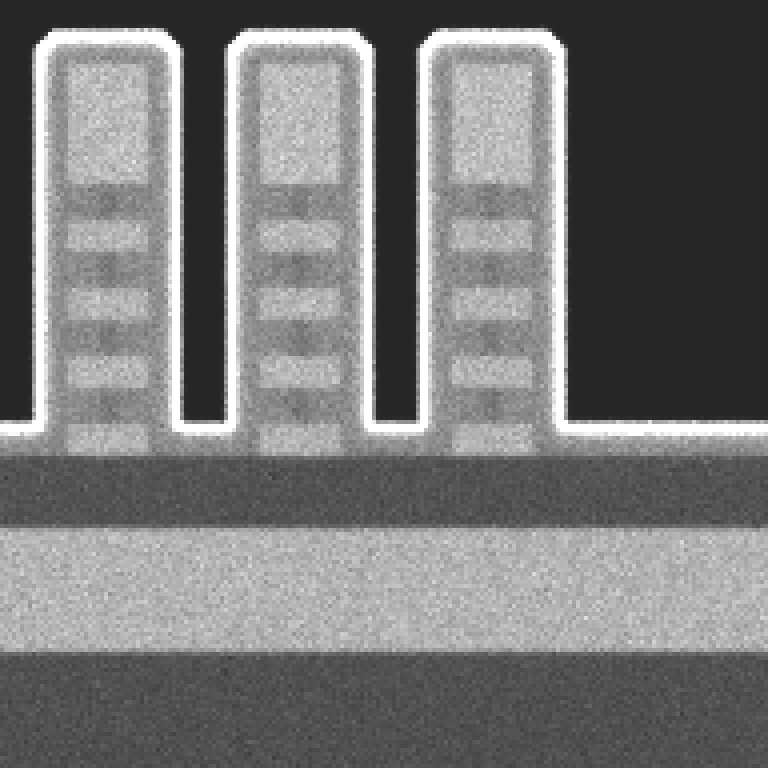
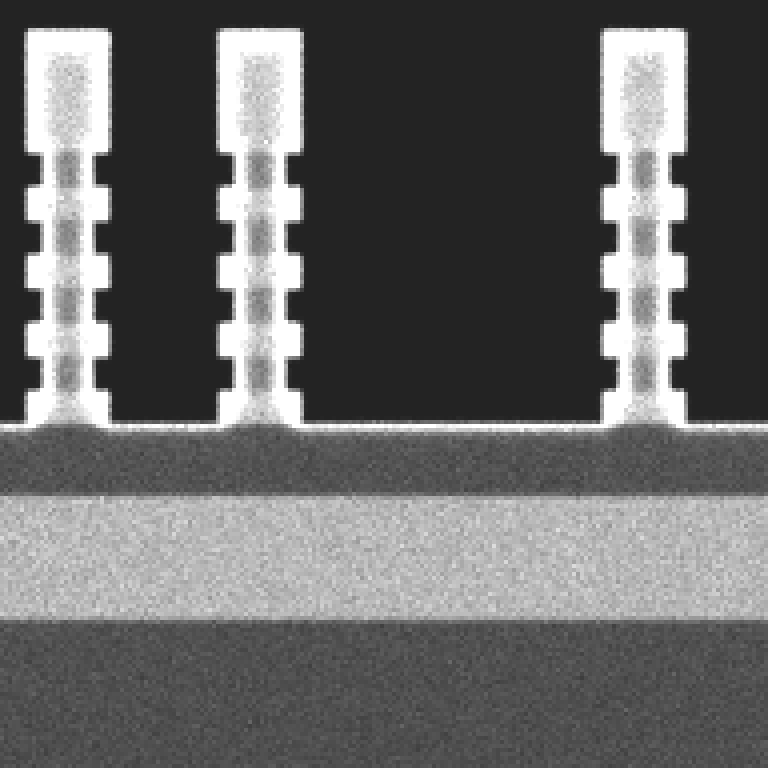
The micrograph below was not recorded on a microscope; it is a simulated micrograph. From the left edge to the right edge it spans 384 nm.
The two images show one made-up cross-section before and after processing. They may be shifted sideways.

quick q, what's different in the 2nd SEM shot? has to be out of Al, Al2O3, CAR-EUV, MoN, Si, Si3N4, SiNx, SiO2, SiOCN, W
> Si3N4 removed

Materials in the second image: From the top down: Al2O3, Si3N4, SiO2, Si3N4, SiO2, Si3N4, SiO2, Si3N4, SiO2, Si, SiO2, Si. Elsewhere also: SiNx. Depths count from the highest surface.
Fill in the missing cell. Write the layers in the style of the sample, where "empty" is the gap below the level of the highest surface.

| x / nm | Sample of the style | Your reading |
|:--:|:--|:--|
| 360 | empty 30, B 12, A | empty 196, Si 36, SiO2 62, Si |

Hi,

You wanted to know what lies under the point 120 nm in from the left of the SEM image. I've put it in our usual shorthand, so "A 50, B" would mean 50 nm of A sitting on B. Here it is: Al2O3 60, Si3N4 18, SiO2 16, Si3N4 18, SiO2 16, Si3N4 18, SiO2 16, Si3N4 18, SiO2 16, Si 36, SiO2 62, Si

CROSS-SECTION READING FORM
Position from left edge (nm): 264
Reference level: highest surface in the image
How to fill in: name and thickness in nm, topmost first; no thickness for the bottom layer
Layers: empty 196, Si 36, SiO2 62, Si